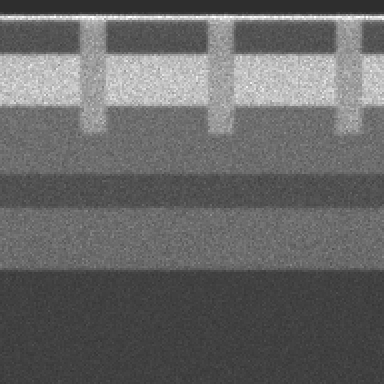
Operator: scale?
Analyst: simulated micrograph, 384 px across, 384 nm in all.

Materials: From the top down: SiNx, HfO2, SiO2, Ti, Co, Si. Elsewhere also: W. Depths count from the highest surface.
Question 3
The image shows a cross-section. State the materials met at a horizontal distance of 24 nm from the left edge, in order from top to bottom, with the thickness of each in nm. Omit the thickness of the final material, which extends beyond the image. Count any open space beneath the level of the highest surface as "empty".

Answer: SiNx 38, HfO2 52, SiO2 68, Ti 34, Co 62, Si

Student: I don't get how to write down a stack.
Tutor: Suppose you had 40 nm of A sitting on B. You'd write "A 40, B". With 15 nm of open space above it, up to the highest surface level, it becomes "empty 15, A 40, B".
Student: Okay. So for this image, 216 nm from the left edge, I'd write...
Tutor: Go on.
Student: W 118, SiO2 40, Ti 34, Co 62, Si